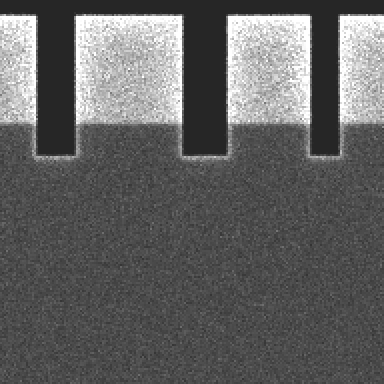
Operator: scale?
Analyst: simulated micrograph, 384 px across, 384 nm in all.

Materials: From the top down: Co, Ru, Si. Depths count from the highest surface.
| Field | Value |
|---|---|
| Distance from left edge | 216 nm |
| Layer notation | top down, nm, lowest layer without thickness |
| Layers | empty 140, Si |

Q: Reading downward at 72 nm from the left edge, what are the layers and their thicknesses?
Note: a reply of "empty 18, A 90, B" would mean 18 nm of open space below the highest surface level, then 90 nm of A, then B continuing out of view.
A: empty 140, Si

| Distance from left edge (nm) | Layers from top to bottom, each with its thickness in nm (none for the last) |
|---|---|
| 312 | empty 140, Si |